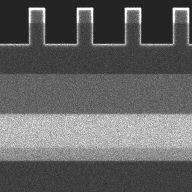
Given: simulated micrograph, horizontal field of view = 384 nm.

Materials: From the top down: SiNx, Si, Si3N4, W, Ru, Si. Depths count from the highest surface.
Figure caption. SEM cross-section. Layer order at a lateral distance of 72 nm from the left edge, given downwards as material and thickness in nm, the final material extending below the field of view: SiNx 30, Si 102, Si3N4 80, W 68, Ru 26, Si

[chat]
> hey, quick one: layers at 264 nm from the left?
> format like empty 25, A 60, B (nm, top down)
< SiNx 30, Si 102, Si3N4 80, W 68, Ru 26, Si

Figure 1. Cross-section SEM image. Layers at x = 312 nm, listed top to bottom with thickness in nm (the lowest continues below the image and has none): empty 72, Si 60, Si3N4 80, W 68, Ru 26, Si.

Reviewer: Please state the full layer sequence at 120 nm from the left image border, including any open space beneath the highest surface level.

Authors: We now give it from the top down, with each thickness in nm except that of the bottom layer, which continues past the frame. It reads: empty 72, Si 60, Si3N4 80, W 68, Ru 26, Si